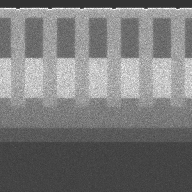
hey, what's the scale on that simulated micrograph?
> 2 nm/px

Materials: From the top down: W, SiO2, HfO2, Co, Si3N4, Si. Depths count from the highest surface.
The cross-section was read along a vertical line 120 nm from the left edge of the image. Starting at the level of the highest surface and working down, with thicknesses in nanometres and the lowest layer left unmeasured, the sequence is W 20, SiO2 80, HfO2 80, Co 60, Si3N4 28, Si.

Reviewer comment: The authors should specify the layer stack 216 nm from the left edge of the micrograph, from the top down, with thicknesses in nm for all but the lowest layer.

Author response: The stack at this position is W 198, Co 42, Si3N4 28, Si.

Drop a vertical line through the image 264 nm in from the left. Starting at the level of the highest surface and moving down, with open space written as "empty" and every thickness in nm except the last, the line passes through W 20, SiO2 80, HfO2 80, Co 60, Si3N4 28, Si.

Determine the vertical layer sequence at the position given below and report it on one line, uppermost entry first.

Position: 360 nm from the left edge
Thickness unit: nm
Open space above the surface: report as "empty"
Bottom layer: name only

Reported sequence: W 198, Co 42, Si3N4 28, Si